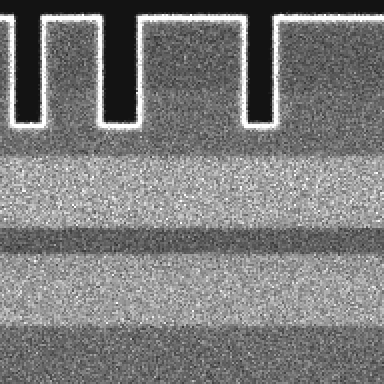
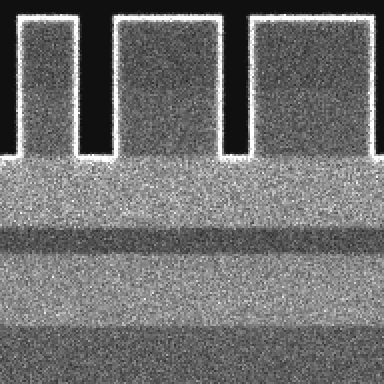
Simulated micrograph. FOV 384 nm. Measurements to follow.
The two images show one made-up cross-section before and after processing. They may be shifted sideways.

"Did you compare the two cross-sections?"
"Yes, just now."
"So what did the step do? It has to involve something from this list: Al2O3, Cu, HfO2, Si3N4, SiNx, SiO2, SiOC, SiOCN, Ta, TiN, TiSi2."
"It removed Si3N4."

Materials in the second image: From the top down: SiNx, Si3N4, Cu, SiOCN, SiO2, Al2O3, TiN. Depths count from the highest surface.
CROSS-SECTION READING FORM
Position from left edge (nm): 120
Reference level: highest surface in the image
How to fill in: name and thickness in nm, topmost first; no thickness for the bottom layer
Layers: SiNx 74, Si3N4 66, Cu 72, SiOCN 26, SiO2 18, Al2O3 54, TiN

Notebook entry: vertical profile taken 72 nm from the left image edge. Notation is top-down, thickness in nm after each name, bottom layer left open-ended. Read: SiNx 74, Si3N4 66, Cu 72, SiOCN 26, SiO2 18, Al2O3 54, TiN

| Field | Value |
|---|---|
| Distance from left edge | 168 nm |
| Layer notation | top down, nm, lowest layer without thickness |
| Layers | SiNx 74, Si3N4 66, Cu 72, SiOCN 26, SiO2 18, Al2O3 54, TiN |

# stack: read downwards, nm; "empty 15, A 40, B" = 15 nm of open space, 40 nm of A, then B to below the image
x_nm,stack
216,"SiNx 74, Si3N4 66, Cu 72, SiOCN 26, SiO2 18, Al2O3 54, TiN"